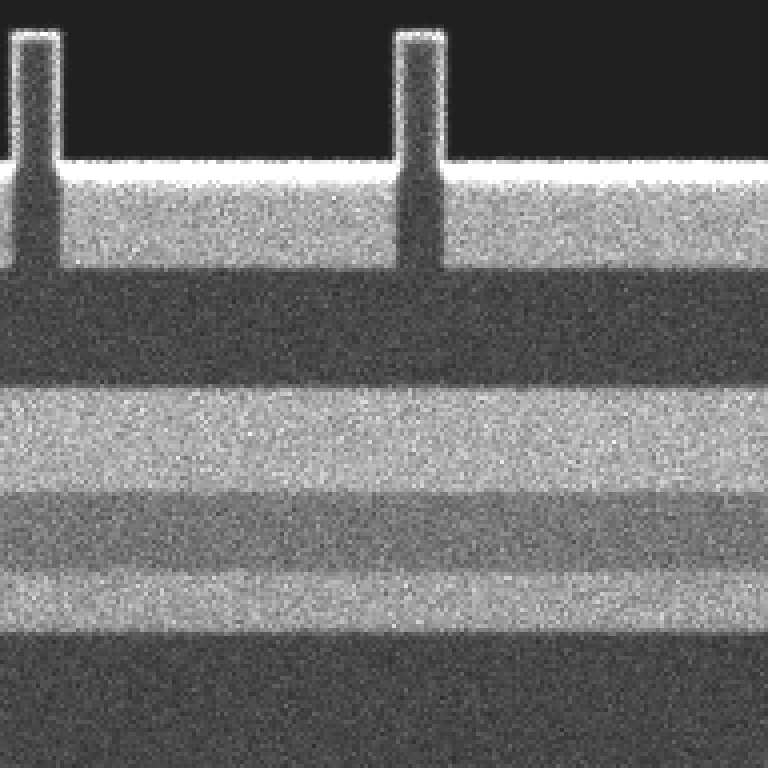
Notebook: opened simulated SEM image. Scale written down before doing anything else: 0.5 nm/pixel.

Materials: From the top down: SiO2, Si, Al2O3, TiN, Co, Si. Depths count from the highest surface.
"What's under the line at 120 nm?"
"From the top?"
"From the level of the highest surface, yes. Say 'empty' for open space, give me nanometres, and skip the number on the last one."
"empty 66, SiO2 52, Si 60, Al2O3 52, TiN 40, Co 30, Si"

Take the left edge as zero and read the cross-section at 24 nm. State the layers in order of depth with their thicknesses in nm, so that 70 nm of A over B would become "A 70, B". Si 178, Al2O3 52, TiN 40, Co 30, Si